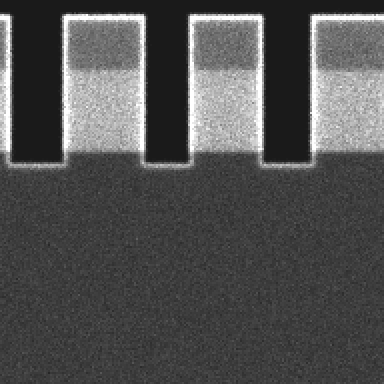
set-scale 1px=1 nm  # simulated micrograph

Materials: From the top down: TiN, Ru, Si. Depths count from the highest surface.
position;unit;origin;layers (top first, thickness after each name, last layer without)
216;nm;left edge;TiN 54, Ru 82, Si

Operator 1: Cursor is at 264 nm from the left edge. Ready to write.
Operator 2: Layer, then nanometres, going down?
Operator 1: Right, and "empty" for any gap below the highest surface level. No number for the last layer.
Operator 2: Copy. empty 148, Si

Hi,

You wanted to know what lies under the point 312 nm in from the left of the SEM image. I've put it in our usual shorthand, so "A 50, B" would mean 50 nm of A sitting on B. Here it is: TiN 54, Ru 82, Si